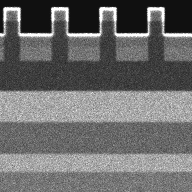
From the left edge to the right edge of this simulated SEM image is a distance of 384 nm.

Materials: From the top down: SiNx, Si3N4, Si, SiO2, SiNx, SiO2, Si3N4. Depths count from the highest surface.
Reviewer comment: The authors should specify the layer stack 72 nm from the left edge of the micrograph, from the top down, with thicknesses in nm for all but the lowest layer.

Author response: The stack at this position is empty 52, SiNx 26, Si3N4 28, Si 60, SiO2 62, SiNx 64, SiO2 36, Si3N4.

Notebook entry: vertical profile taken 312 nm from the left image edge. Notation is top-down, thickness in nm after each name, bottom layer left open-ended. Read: SiNx 26, Si 140, SiO2 62, SiNx 64, SiO2 36, Si3N4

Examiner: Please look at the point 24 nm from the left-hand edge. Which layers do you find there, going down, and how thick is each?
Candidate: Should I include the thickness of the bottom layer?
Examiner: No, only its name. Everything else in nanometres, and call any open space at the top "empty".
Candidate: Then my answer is SiNx 26, Si 140, SiO2 62, SiNx 64, SiO2 36, Si3N4